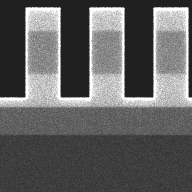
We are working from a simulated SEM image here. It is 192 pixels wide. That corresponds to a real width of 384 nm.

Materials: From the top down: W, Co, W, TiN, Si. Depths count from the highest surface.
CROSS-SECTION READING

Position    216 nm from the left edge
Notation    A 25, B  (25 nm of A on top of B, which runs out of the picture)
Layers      W 46, Co 86, W 66, TiN 56, Si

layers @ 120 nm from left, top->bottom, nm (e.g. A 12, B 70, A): empty 180, W 18, TiN 56, Si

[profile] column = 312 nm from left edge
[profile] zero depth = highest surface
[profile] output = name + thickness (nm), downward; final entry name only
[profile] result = W 46, Co 86, W 66, TiN 56, Si